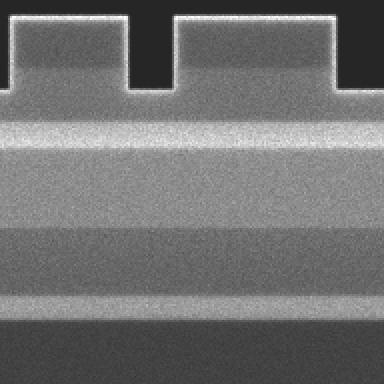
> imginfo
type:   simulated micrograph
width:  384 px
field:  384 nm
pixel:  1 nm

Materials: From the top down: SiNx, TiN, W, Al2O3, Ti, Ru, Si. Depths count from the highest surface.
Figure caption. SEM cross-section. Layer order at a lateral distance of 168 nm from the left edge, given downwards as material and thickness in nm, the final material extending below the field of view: empty 74, TiN 32, W 26, Al2O3 80, Ti 68, Ru 24, Si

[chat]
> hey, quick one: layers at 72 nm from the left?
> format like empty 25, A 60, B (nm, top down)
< SiNx 52, TiN 54, W 26, Al2O3 80, Ti 68, Ru 24, Si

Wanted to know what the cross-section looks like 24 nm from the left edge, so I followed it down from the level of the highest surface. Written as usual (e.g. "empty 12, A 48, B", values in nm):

SiNx 52, TiN 54, W 26, Al2O3 80, Ti 68, Ru 24, Si